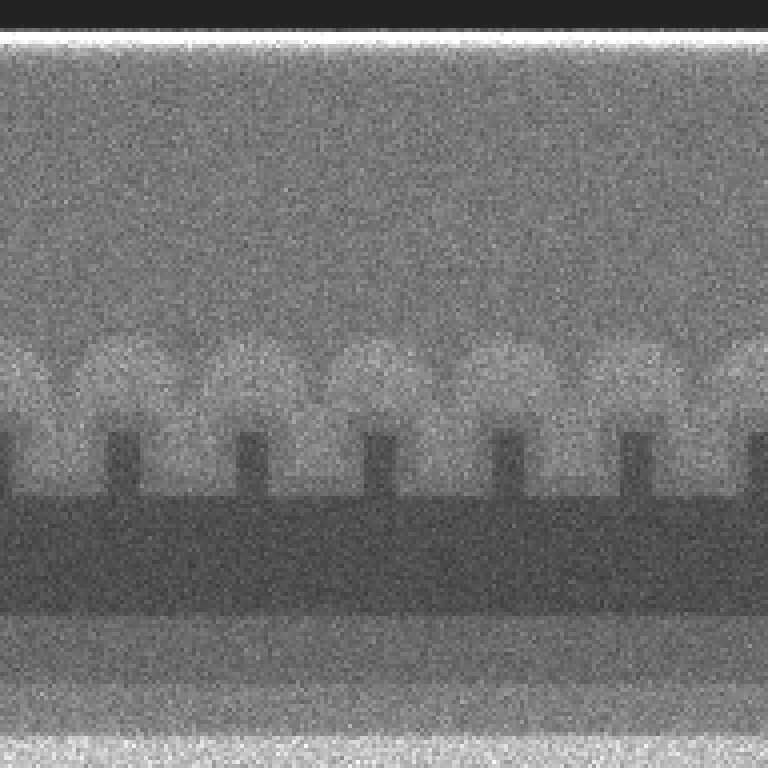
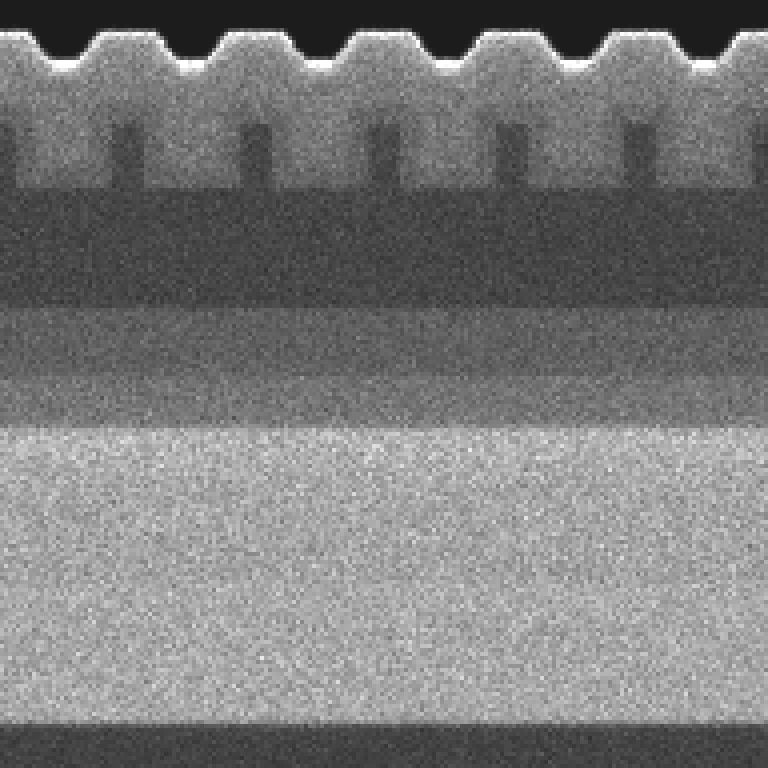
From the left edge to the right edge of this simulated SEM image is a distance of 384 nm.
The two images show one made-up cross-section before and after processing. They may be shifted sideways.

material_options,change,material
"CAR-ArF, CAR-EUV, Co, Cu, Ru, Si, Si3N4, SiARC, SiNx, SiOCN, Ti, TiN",removed,SiARC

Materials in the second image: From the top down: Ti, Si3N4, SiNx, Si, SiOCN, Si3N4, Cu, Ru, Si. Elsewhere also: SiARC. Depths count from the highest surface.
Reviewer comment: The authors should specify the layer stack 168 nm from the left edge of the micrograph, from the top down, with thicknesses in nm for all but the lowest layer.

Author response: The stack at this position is empty 12, Ti 22, Si3N4 34, SiNx 10, Si 60, SiOCN 34, Si3N4 26, Cu 78, Ru 70, Si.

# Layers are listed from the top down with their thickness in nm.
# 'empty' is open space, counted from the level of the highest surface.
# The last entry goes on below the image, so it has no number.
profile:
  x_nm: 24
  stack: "empty 14, Ti 22, Si3N4 32, SiNx 10, Si 60, SiOCN 34, Si3N4 26, Cu 78, Ru 70, Si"